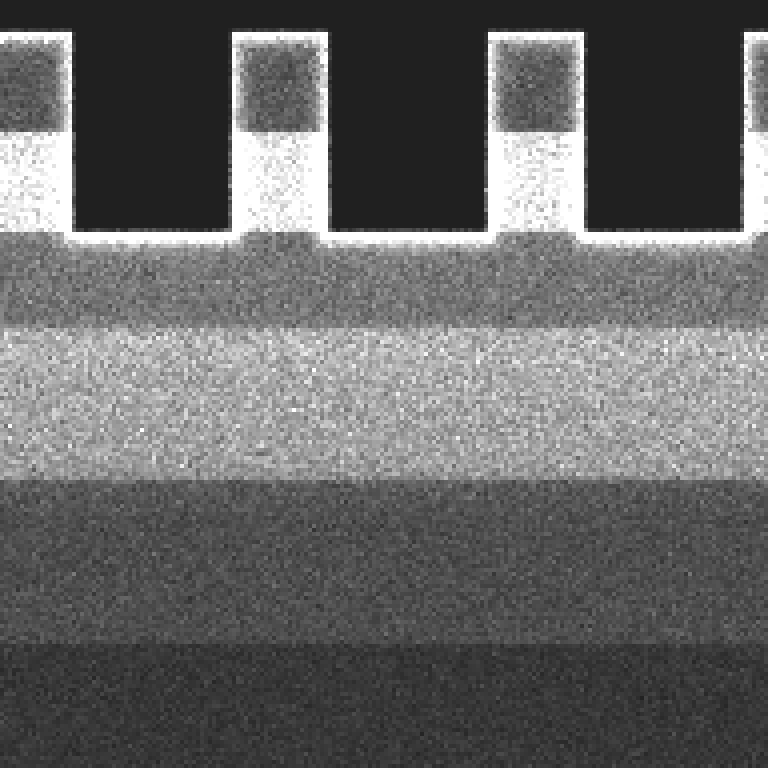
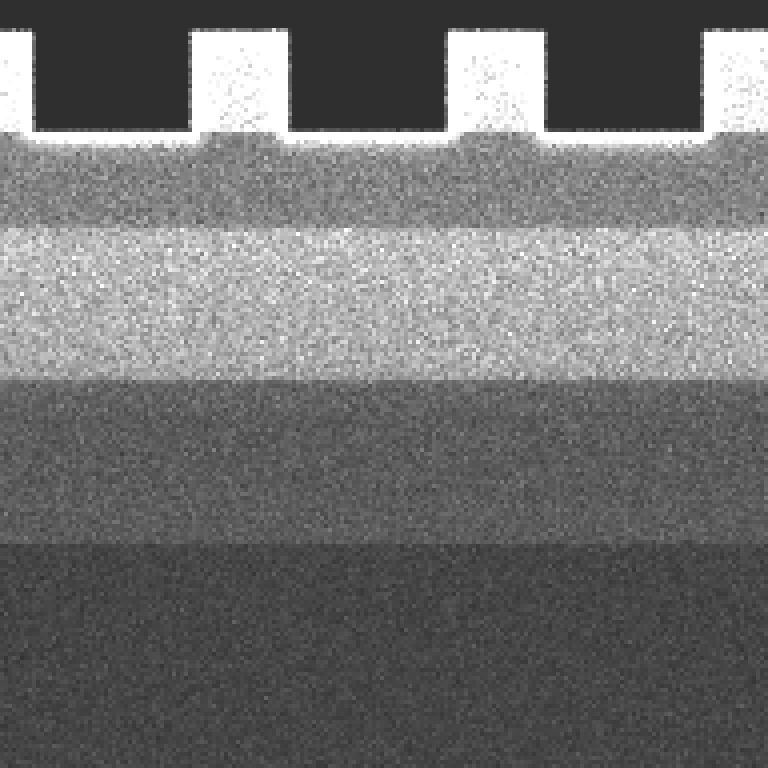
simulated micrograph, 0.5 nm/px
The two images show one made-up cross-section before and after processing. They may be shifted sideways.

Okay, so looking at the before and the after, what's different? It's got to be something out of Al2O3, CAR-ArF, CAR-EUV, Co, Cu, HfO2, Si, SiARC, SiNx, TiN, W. SiARC, removed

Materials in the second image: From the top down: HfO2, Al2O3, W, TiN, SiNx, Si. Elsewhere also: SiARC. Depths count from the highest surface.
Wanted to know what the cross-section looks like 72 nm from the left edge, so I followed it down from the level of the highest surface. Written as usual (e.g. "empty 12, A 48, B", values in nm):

empty 50, Al2O3 48, W 76, TiN 16, SiNx 66, Si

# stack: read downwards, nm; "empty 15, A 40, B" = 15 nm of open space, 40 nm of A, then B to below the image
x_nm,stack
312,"empty 50, Al2O3 48, W 76, TiN 16, SiNx 66, Si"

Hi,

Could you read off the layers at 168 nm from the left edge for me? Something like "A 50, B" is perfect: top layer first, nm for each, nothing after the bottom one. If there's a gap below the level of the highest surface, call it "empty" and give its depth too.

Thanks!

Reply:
empty 50, Al2O3 48, W 76, TiN 16, SiNx 66, Si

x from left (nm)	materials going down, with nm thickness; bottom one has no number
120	HfO2 50, Al2O3 48, W 76, TiN 16, SiNx 66, Si